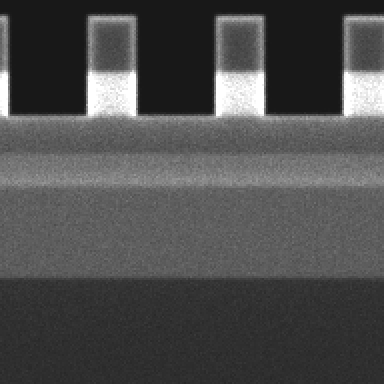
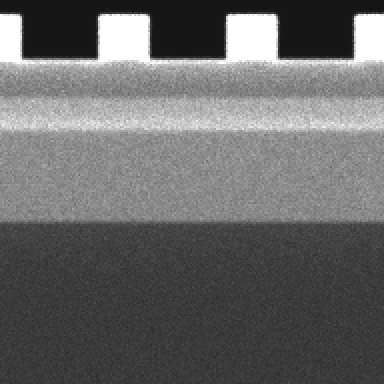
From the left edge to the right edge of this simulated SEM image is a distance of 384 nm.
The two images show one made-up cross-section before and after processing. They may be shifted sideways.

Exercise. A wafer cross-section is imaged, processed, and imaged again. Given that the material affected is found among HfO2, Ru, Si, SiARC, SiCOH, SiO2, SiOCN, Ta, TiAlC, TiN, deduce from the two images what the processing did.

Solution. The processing removed SiARC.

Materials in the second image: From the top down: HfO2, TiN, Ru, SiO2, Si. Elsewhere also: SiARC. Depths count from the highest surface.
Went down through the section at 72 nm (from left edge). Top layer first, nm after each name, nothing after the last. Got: empty 44, TiN 38, Ru 32, SiO2 92, Si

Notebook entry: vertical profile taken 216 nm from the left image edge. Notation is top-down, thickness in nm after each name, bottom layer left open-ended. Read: empty 44, TiN 38, Ru 32, SiO2 92, Si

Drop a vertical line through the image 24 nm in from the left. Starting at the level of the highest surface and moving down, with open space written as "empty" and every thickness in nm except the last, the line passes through empty 44, TiN 38, Ru 32, SiO2 92, Si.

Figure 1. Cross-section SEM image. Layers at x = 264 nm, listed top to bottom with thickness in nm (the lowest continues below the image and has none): HfO2 44, TiN 38, Ru 32, SiO2 92, Si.